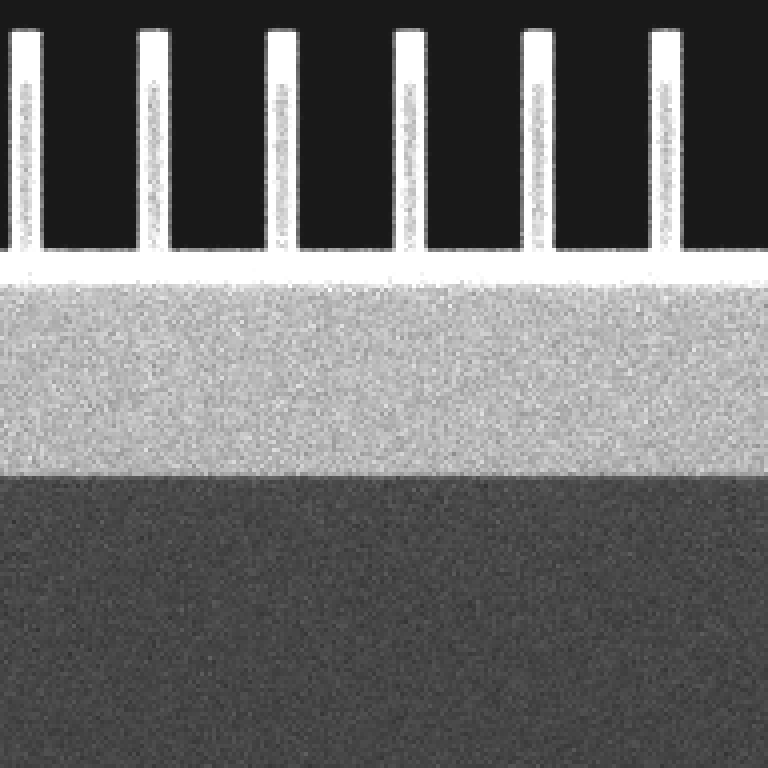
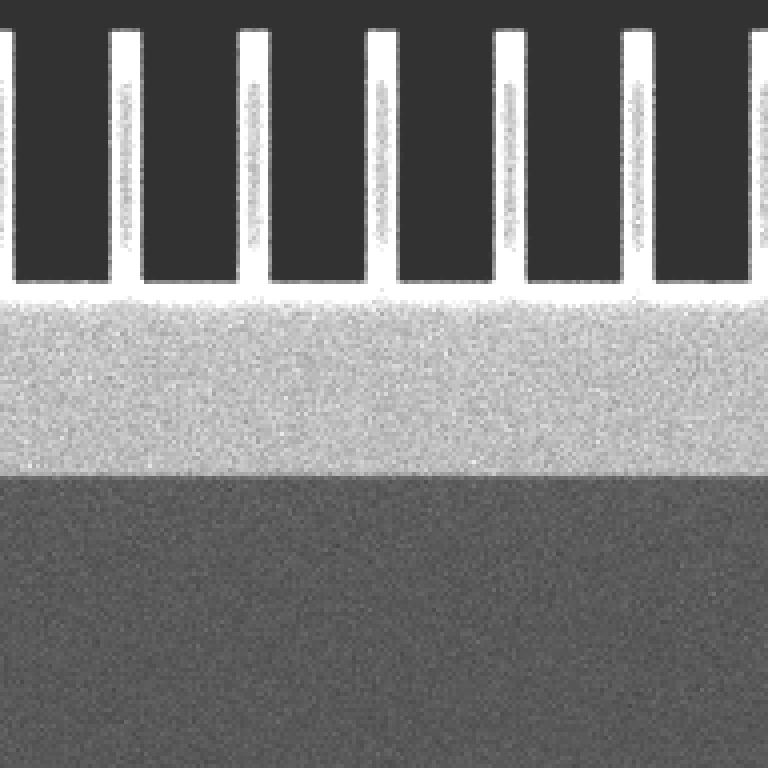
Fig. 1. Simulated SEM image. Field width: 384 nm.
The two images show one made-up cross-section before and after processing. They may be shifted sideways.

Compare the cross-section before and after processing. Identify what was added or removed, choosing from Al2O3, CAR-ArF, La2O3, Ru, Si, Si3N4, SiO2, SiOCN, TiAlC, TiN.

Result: Ru removed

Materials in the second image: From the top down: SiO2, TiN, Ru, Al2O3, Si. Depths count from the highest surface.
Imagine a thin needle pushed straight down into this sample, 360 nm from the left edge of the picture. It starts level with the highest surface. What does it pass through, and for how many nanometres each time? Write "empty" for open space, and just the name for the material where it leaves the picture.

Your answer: empty 126, Al2O3 96, Si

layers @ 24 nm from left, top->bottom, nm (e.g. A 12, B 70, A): empty 126, Al2O3 96, Si